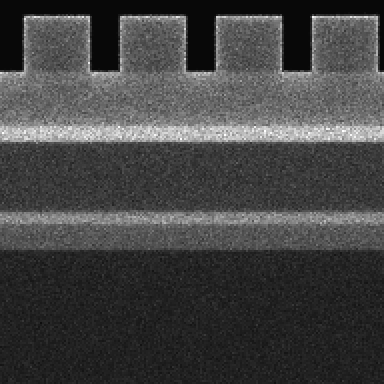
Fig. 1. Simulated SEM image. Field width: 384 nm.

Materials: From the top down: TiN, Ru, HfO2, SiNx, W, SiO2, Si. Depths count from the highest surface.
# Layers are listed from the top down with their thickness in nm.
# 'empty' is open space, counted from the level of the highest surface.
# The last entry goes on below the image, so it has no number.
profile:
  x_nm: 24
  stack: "TiN 56, Ru 54, HfO2 16, SiNx 70, W 12, SiO2 26, Si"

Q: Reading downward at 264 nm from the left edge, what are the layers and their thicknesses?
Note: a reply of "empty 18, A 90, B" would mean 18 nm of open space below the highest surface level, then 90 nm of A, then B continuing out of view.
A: TiN 56, Ru 54, HfO2 16, SiNx 70, W 12, SiO2 26, Si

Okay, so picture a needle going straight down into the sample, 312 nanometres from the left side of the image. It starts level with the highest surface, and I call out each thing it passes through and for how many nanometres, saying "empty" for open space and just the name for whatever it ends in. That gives TiN 56, Ru 54, HfO2 16, SiNx 70, W 12, SiO2 26, Si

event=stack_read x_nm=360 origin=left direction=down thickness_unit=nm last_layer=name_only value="TiN 56, Ru 54, HfO2 16, SiNx 70, W 12, SiO2 26, Si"